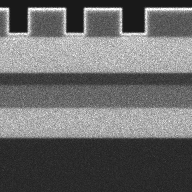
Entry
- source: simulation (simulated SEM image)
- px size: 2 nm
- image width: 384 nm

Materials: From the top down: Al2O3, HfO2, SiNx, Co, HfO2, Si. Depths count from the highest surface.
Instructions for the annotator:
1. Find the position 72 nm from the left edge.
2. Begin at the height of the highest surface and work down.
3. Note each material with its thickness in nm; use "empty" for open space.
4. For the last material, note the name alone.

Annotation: Al2O3 58, HfO2 72, SiNx 24, Co 46, HfO2 60, Si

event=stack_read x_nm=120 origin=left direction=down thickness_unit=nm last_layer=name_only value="Al2O3 58, HfO2 72, SiNx 24, Co 46, HfO2 60, Si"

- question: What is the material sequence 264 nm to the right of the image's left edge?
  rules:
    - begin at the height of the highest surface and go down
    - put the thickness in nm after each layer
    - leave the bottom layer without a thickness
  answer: empty 50, Al2O3 8, HfO2 72, SiNx 24, Co 46, HfO2 60, Si